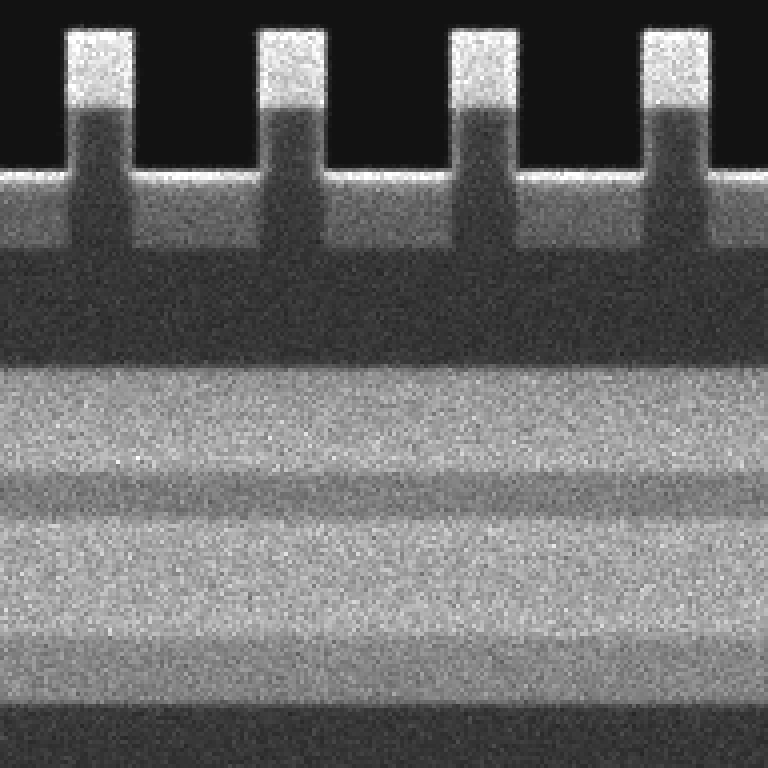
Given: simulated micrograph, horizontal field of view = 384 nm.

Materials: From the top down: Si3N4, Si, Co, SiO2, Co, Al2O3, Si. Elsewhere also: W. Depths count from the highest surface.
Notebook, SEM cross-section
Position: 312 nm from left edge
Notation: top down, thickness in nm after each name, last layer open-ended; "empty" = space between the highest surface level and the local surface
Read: empty 70, Si3N4 38, Si 60, Co 52, SiO2 24, Co 58, Al2O3 34, Si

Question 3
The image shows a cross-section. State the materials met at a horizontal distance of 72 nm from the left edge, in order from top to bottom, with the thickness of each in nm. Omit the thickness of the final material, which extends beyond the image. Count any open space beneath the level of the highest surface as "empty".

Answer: empty 70, Si3N4 38, Si 60, Co 52, SiO2 24, Co 58, Al2O3 34, Si